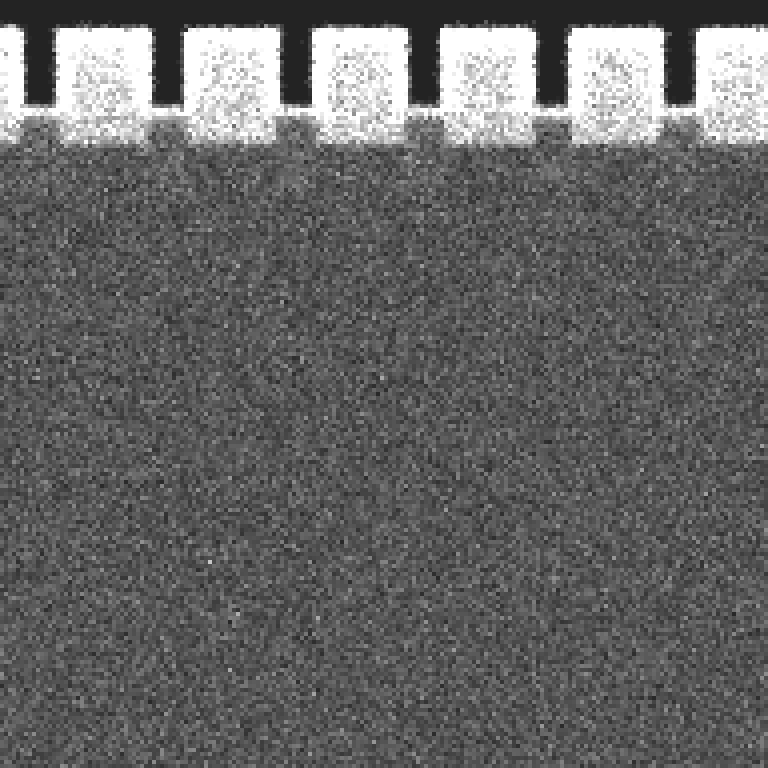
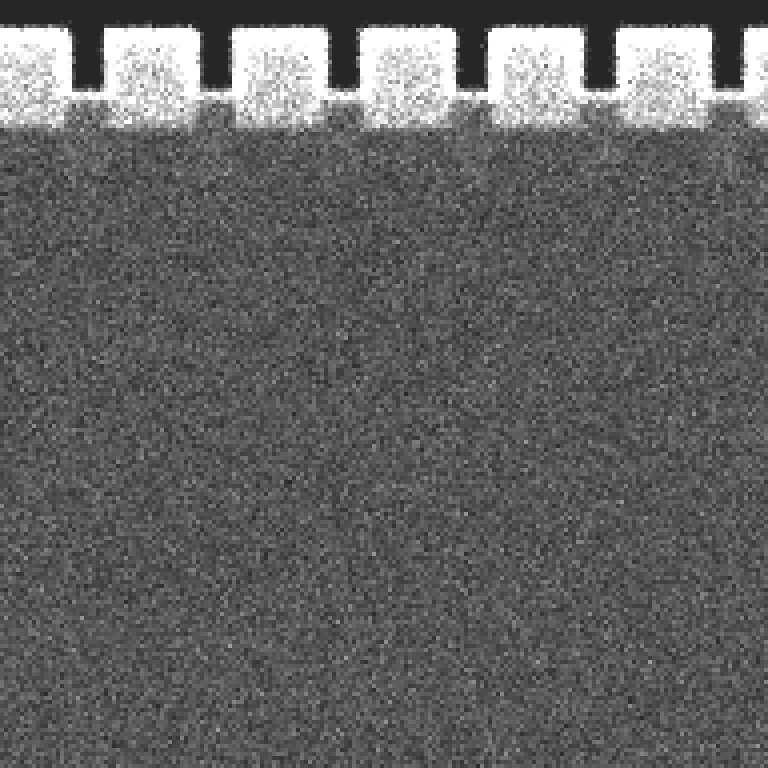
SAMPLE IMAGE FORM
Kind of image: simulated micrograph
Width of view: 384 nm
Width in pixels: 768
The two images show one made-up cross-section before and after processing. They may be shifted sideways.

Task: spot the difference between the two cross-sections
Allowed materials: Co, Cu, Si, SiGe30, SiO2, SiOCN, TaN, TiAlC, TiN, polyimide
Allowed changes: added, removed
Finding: removed Co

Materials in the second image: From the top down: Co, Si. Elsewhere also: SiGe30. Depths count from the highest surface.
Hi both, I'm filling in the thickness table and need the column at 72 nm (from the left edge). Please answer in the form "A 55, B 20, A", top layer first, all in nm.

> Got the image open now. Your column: Co 48, Si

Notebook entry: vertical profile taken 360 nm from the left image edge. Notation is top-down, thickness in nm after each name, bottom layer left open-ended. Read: empty 30, SiGe30 42, Si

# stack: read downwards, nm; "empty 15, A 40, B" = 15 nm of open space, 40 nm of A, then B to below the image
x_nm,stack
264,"Co 48, Si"